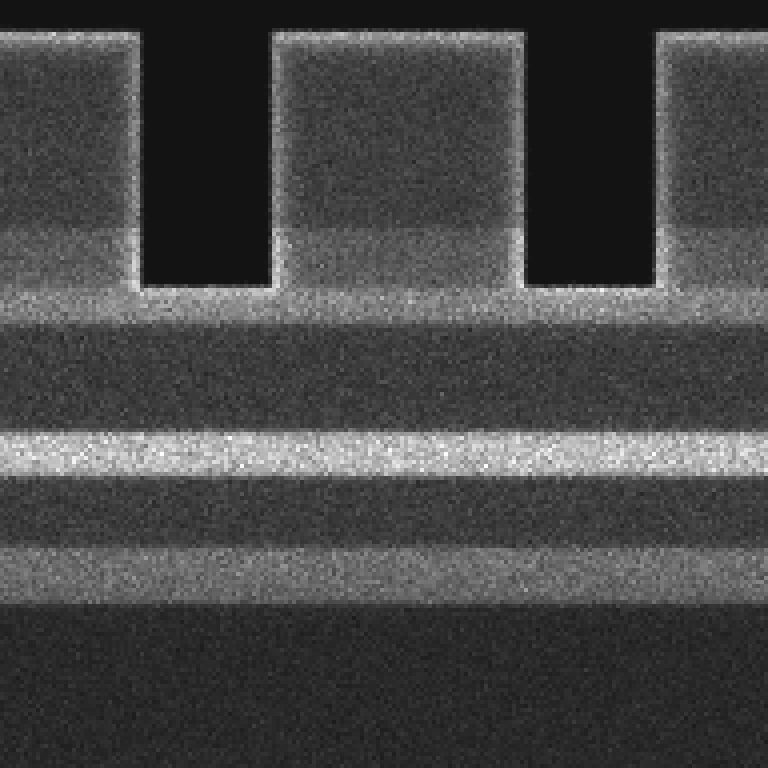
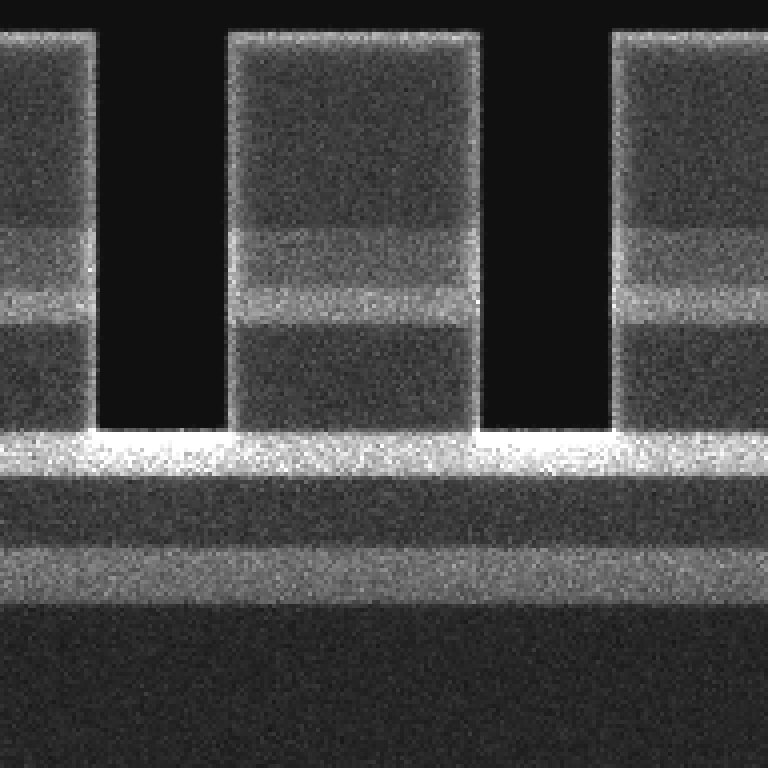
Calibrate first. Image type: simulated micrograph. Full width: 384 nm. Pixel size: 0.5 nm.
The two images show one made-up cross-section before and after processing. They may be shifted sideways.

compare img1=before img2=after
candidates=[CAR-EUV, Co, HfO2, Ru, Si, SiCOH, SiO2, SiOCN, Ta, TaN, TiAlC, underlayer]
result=removed:Co and SiOCN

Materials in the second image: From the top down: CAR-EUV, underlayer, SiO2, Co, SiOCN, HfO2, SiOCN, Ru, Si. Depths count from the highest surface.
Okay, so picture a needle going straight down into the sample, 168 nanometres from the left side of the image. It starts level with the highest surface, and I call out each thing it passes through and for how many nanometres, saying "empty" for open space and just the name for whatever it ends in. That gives CAR-EUV 46, underlayer 52, SiO2 30, Co 18, SiOCN 54, HfO2 22, SiOCN 36, Ru 28, Si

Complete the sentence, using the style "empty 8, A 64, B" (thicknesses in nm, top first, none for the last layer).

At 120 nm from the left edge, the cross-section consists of CAR-EUV 46, underlayer 52, SiO2 30, Co 18, SiOCN 54, HfO2 22, SiOCN 36, Ru 28, Si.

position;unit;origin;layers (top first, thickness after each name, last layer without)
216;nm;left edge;CAR-EUV 46, underlayer 52, SiO2 30, Co 18, SiOCN 54, HfO2 22, SiOCN 36, Ru 28, Si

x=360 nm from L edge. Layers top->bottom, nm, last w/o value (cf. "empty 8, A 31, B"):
CAR-EUV 46, underlayer 52, SiO2 30, Co 18, SiOCN 54, HfO2 22, SiOCN 36, Ru 28, Si